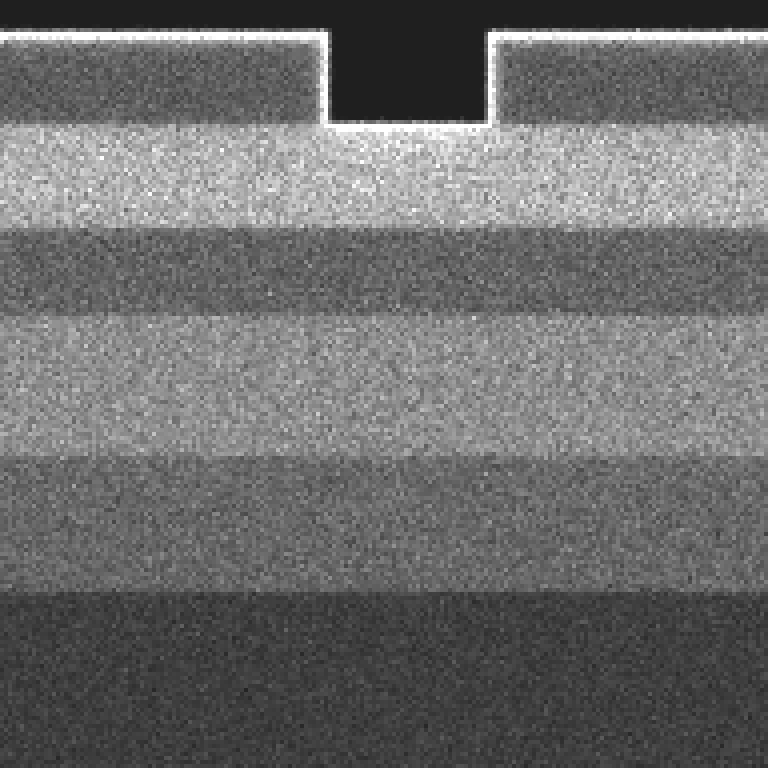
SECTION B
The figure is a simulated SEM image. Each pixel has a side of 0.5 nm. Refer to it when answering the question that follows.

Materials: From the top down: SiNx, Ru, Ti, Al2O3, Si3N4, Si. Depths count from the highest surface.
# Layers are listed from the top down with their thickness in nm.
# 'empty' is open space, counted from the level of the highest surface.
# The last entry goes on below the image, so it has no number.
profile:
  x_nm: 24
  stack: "SiNx 46, Ru 52, Ti 44, Al2O3 70, Si3N4 68, Si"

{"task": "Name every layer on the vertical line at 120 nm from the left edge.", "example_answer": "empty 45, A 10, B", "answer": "SiNx 46, Ru 52, Ti 44, Al2O3 70, Si3N4 68, Si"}